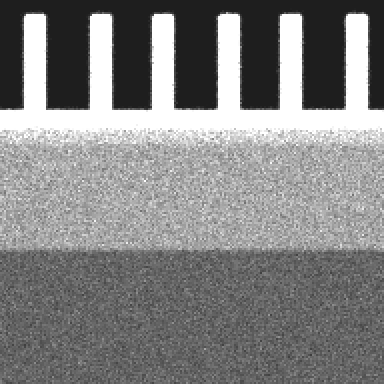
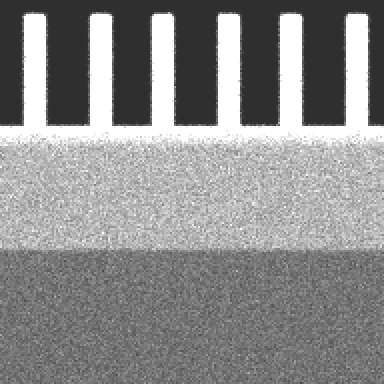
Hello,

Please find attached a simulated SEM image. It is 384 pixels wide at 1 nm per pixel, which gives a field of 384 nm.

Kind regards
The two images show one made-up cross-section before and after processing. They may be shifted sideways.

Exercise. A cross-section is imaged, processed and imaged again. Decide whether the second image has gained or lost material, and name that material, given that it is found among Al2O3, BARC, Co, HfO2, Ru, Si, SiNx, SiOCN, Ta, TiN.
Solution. removed: Co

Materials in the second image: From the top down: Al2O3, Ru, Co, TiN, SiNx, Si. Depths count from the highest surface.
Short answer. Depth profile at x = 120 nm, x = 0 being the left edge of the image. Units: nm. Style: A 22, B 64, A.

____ empty 112, TiN 16, SiNx 106, Si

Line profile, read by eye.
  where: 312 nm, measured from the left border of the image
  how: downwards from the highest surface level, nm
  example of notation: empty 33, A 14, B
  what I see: empty 112, TiN 16, SiNx 106, Si